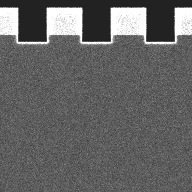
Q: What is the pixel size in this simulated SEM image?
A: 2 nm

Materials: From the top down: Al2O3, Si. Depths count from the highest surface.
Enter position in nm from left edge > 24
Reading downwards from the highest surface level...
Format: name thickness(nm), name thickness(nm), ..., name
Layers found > Al2O3 54, Si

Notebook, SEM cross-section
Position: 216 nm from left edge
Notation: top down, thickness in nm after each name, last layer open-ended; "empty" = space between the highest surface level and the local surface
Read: empty 68, Si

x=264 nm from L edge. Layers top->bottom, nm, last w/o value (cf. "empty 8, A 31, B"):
Al2O3 54, Si